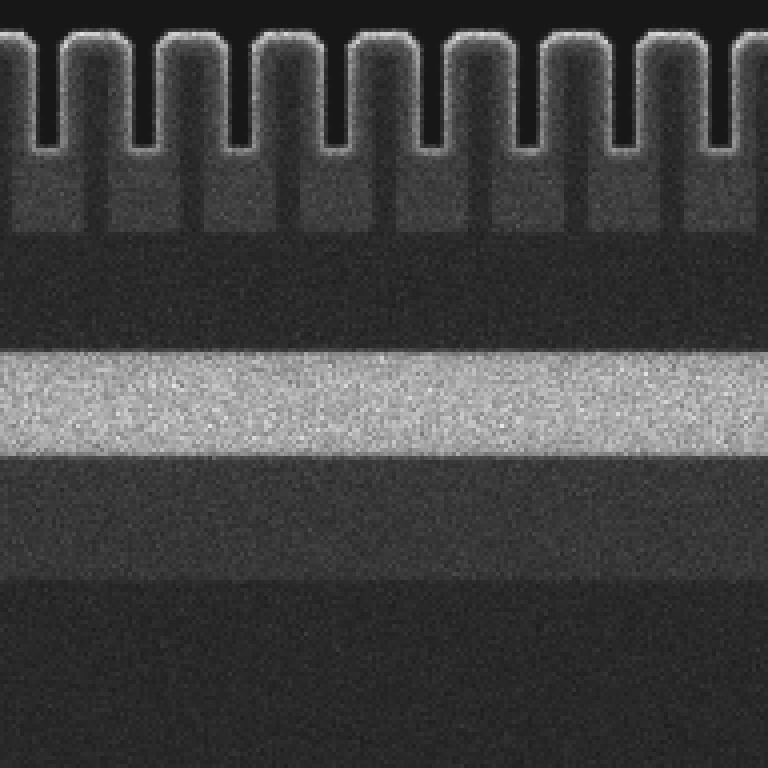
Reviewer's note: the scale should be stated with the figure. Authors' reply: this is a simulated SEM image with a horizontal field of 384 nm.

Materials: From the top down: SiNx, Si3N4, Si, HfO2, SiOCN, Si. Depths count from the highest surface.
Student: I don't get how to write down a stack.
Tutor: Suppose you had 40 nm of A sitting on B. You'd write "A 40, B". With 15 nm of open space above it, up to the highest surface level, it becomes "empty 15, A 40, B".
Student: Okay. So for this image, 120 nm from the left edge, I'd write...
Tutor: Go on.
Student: empty 58, SiNx 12, Si3N4 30, Si 60, HfO2 52, SiOCN 62, Si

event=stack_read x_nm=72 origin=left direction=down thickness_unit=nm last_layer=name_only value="empty 58, SiNx 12, Si3N4 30, Si 60, HfO2 52, SiOCN 62, Si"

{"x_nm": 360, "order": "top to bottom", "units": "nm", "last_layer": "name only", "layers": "empty 58, SiNx 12, Si3N4 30, Si 60, HfO2 52, SiOCN 62, Si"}